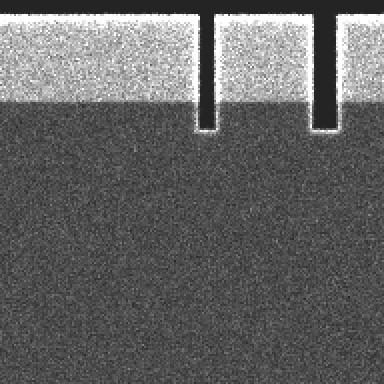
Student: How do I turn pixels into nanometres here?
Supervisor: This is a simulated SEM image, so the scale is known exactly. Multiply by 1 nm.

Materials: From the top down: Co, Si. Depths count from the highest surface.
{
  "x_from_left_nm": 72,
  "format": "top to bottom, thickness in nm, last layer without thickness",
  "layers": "Co 86, Si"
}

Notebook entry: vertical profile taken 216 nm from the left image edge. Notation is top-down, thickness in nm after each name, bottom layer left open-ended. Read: Co 86, Si